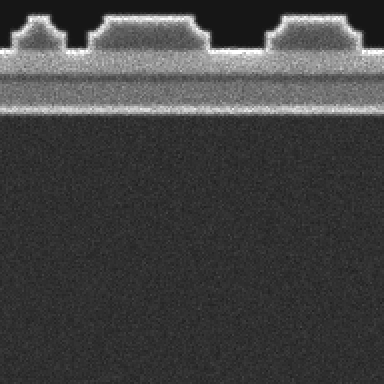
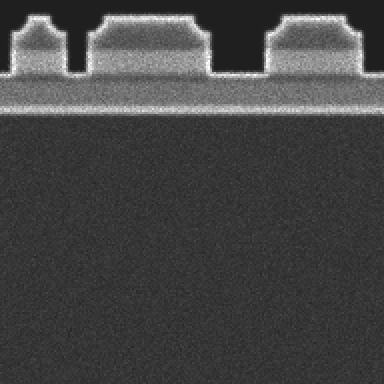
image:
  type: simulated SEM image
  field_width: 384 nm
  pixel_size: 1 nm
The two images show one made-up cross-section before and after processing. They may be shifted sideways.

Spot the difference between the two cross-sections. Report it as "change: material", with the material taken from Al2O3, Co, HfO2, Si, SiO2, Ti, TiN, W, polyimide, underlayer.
removed: W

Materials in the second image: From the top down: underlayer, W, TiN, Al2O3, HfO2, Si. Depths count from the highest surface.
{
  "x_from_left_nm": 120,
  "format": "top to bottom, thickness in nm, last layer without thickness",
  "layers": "underlayer 34, W 24, TiN 8, Al2O3 24, HfO2 8, Si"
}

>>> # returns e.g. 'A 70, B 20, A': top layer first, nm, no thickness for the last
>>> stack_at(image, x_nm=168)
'underlayer 34, W 24, TiN 8, Al2O3 24, HfO2 8, Si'